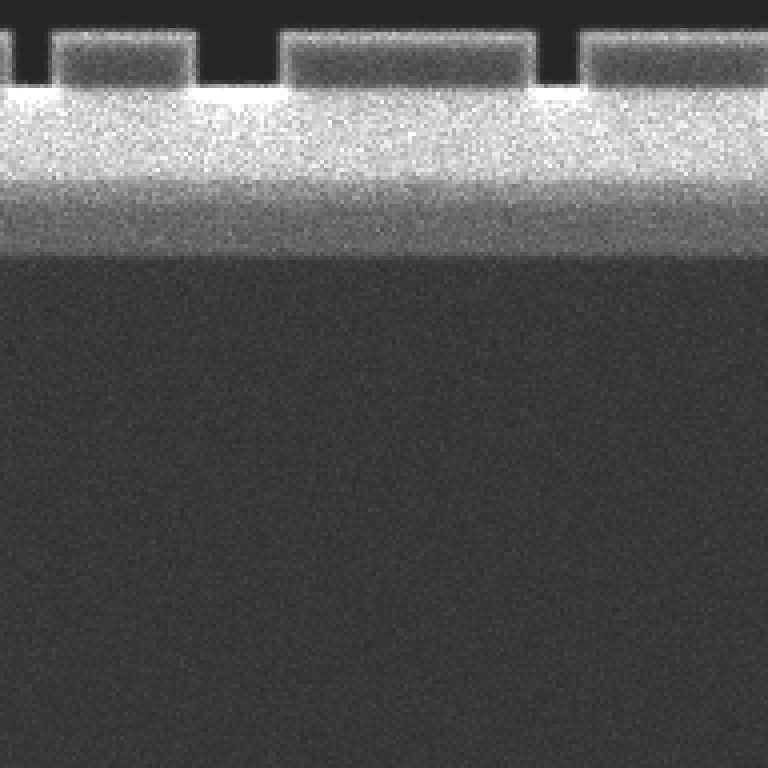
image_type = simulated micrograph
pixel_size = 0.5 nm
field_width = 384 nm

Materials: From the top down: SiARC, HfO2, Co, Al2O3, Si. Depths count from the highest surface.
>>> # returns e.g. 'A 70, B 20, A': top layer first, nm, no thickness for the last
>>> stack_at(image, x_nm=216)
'SiARC 28, HfO2 46, Co 12, Al2O3 26, Si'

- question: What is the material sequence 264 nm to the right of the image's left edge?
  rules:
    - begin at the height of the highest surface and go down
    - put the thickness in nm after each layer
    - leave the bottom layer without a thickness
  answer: SiARC 28, HfO2 46, Co 12, Al2O3 26, Si